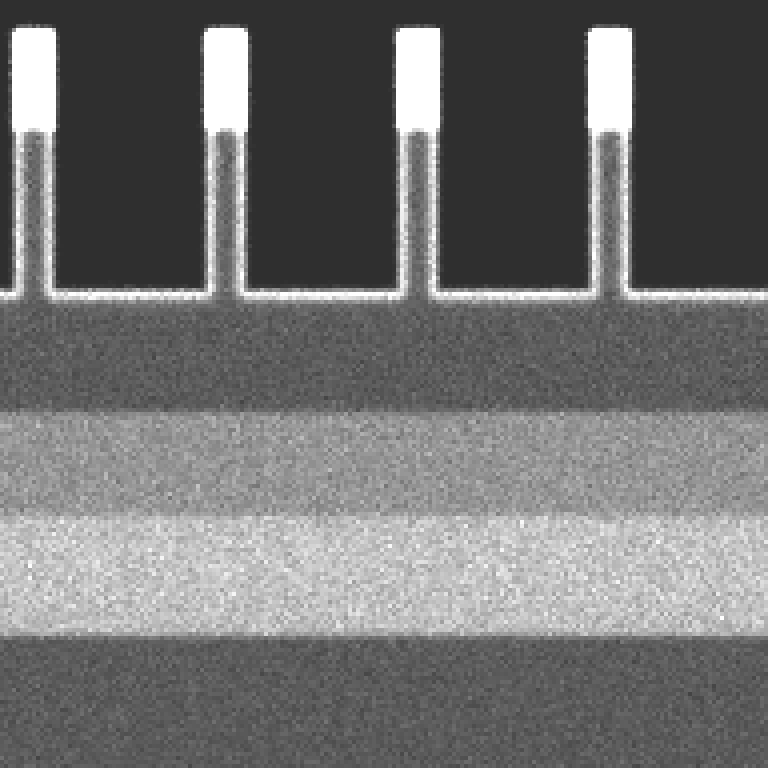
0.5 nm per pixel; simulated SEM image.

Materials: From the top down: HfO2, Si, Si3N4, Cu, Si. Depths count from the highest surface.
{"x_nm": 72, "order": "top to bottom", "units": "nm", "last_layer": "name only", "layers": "empty 130, Si 60, Si3N4 52, Cu 60, Si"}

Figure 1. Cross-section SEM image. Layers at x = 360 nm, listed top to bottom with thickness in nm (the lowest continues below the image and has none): empty 130, Si 60, Si3N4 52, Cu 60, Si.